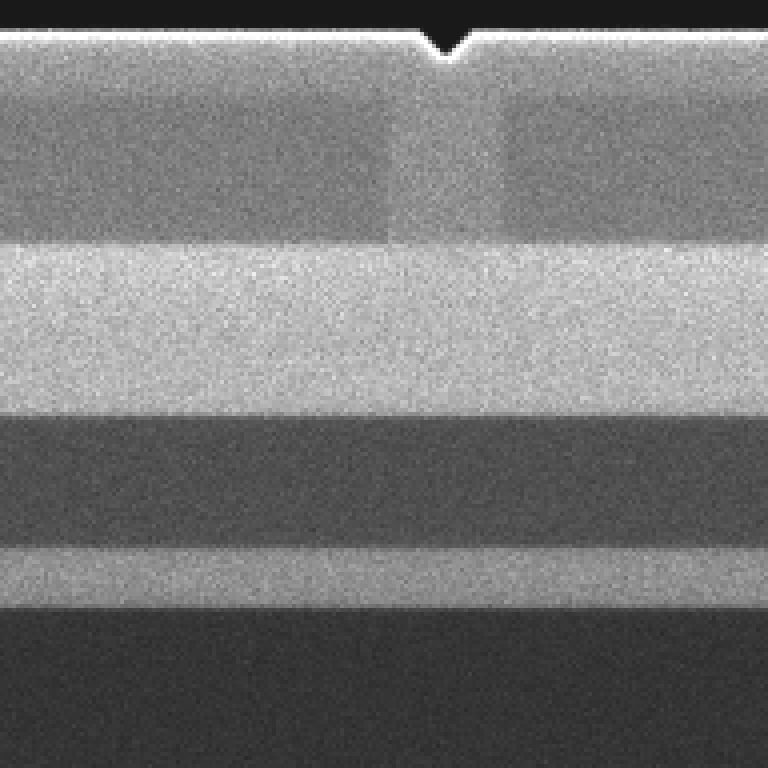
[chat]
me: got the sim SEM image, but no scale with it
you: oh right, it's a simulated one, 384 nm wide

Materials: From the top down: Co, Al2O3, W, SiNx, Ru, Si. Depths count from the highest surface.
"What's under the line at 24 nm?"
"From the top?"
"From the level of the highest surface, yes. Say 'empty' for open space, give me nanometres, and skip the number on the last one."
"Co 32, Al2O3 74, W 86, SiNx 66, Ru 30, Si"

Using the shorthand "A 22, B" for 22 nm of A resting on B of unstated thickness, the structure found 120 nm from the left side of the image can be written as Co 32, Al2O3 74, W 86, SiNx 66, Ru 30, Si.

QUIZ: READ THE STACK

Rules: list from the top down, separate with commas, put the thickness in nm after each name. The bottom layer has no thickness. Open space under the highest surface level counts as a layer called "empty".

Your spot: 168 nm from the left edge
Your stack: Co 32, Al2O3 74, W 86, SiNx 66, Ru 30, Si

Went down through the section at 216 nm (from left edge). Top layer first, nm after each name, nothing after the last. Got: empty 8, Co 98, W 86, SiNx 66, Ru 30, Si